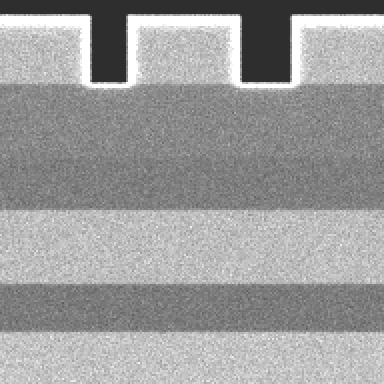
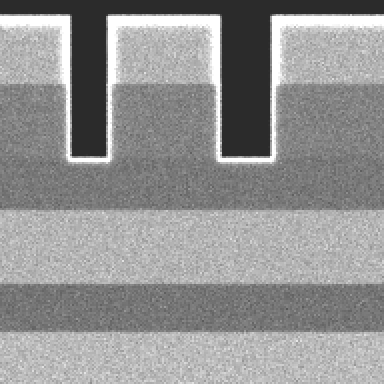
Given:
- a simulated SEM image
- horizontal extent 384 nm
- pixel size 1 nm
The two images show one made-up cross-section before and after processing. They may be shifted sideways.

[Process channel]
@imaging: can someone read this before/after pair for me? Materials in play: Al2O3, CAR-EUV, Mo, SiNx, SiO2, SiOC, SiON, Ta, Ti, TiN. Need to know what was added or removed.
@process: TiN removed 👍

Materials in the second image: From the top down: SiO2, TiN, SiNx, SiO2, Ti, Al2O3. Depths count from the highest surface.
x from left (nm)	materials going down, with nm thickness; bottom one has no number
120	SiO2 68, TiN 74, SiNx 52, SiO2 74, Ti 48, Al2O3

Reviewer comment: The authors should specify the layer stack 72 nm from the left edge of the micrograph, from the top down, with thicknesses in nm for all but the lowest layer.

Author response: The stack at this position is empty 142, SiNx 52, SiO2 74, Ti 48, Al2O3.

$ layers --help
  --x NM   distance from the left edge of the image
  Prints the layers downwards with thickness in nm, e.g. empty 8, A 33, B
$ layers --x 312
SiO2 68, TiN 74, SiNx 52, SiO2 74, Ti 48, Al2O3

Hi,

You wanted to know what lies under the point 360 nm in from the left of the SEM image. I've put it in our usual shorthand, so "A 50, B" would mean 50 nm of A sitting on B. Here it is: SiO2 68, TiN 74, SiNx 52, SiO2 74, Ti 48, Al2O3